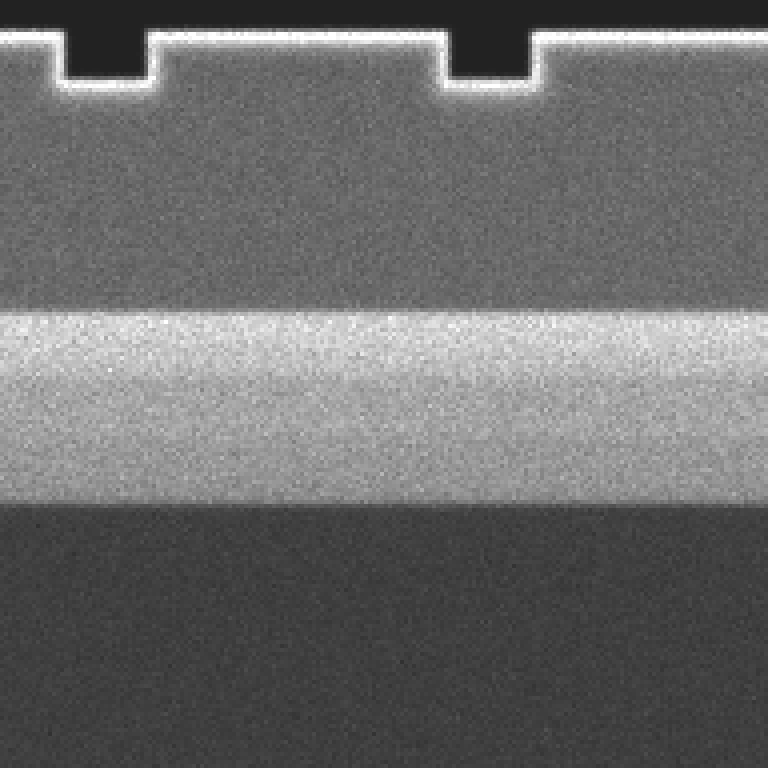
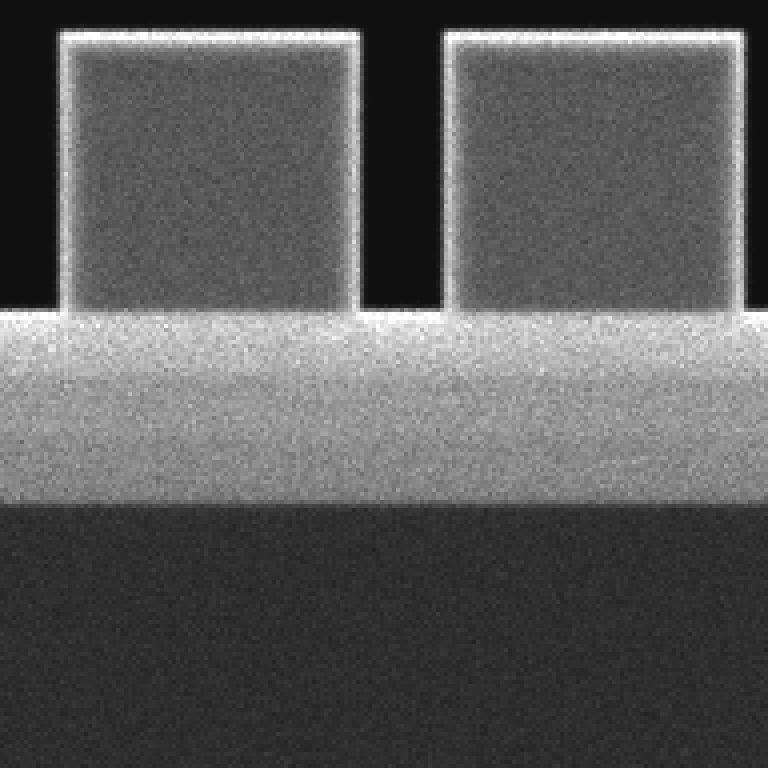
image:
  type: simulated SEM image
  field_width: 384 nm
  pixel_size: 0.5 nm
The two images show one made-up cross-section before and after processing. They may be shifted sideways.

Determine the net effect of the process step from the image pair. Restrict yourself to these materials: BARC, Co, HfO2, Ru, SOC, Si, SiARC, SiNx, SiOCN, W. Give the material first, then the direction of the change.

SOC: removed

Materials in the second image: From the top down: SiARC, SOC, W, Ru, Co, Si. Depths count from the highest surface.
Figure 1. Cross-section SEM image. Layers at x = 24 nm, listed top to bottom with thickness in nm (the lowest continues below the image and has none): empty 140, W 32, Ru 30, Co 34, Si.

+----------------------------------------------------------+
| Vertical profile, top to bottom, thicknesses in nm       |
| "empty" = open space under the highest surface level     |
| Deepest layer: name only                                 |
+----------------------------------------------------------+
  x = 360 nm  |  SiARC 24, SOC 116, W 32, Ru 30, Co 34, Si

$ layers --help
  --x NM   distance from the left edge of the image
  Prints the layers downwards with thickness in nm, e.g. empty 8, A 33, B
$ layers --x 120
SiARC 24, SOC 116, W 32, Ru 30, Co 34, Si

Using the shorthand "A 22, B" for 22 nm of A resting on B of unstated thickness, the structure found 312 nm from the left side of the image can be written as SiARC 24, SOC 116, W 32, Ru 30, Co 34, Si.